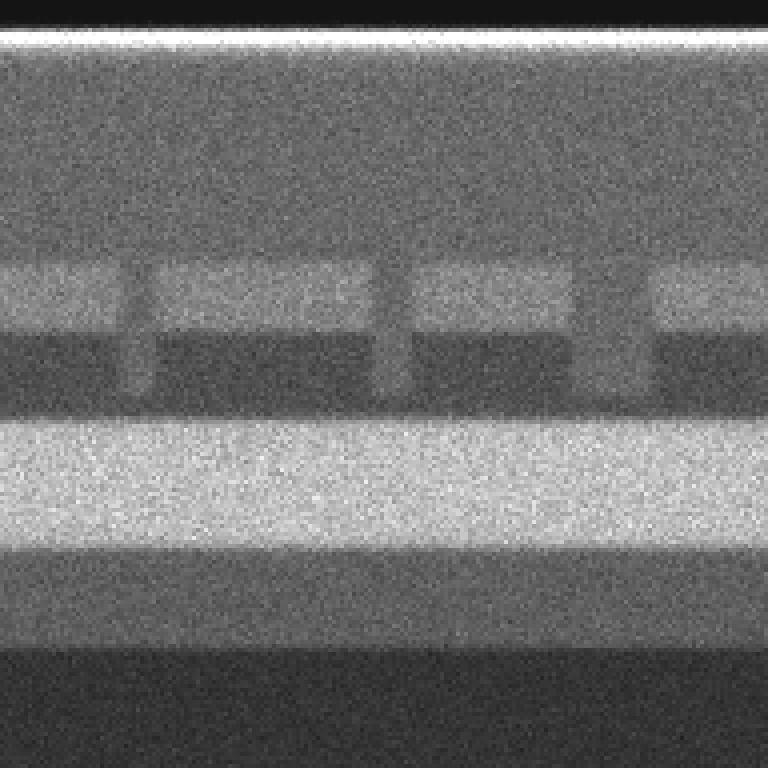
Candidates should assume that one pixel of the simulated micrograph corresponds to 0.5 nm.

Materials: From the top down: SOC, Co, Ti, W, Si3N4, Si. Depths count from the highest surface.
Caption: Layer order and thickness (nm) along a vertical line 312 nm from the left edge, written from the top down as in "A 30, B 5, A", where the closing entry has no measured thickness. SOC 182, Ti 12, W 64, Si3N4 50, Si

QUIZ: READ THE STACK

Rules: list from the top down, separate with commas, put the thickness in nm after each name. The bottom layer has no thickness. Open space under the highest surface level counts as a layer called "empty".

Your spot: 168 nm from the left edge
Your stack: SOC 116, Co 34, Ti 44, W 64, Si3N4 50, Si